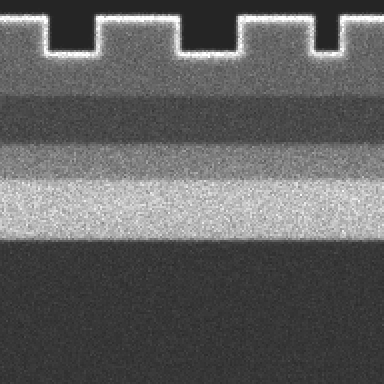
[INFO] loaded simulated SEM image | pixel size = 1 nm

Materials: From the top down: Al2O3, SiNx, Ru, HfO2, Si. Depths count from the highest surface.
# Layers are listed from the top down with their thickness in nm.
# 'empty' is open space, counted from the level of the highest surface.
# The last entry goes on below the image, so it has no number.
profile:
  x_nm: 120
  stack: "Al2O3 80, SiNx 48, Ru 36, HfO2 60, Si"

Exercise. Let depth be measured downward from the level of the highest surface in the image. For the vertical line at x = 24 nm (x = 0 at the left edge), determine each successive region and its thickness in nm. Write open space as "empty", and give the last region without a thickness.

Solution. Al2O3 80, SiNx 48, Ru 36, HfO2 60, Si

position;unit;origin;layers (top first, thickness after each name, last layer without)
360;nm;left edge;Al2O3 80, SiNx 48, Ru 36, HfO2 60, Si